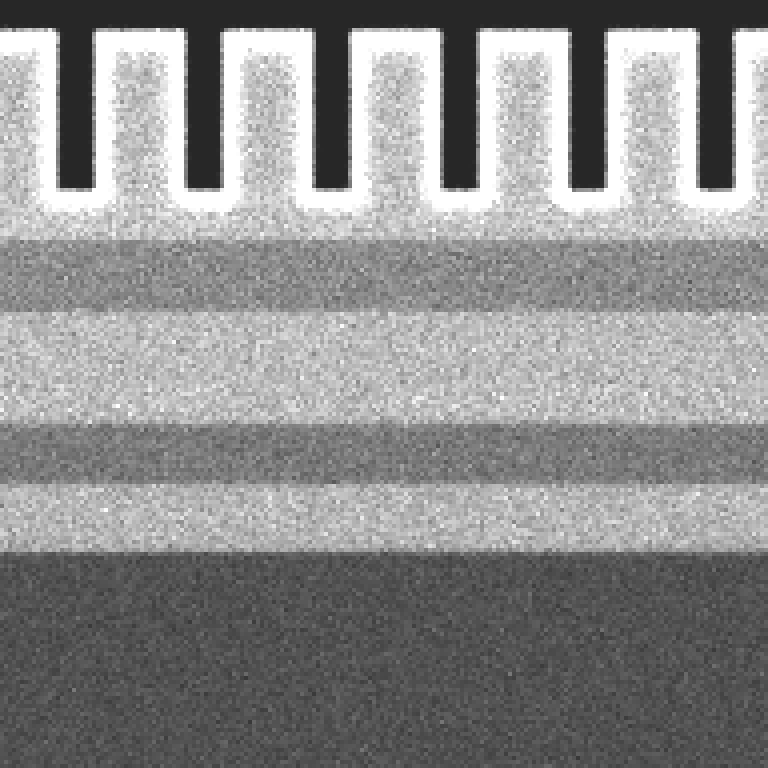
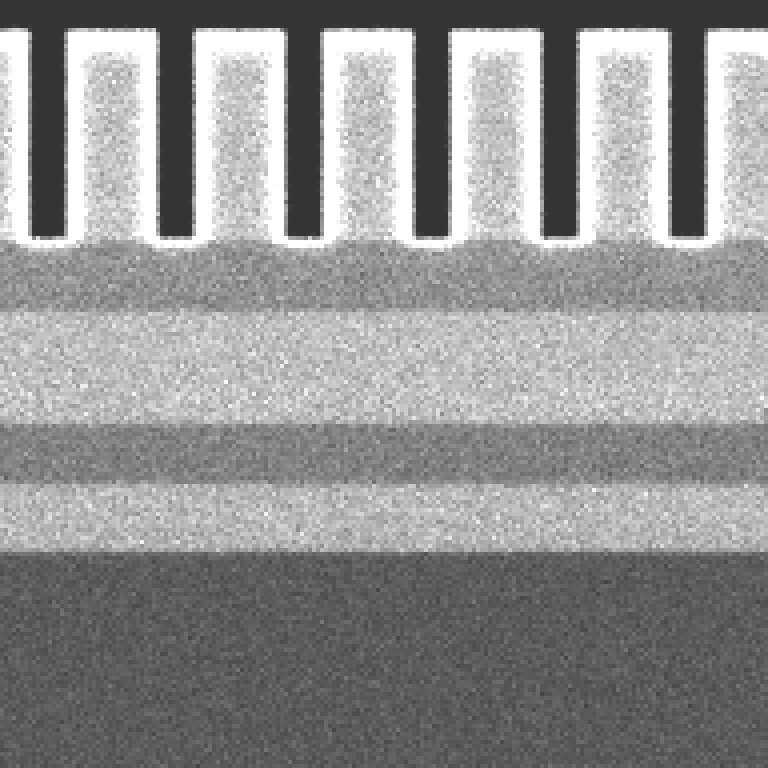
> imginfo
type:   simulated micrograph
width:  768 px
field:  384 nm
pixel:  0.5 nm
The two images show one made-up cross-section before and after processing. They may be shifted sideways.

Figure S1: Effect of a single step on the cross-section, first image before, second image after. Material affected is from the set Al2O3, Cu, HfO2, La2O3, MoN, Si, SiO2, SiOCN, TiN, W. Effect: removed Al2O3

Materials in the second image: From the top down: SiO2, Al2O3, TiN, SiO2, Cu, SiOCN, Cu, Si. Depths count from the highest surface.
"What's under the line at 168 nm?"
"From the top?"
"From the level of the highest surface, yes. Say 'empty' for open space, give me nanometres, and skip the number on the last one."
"SiO2 80, Al2O3 24, TiN 36, SiO2 36, Cu 20, SiOCN 30, Cu 34, Si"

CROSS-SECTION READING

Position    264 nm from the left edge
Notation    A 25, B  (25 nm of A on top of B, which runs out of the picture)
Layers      SiO2 80, Al2O3 24, TiN 36, SiO2 36, Cu 20, SiOCN 30, Cu 34, Si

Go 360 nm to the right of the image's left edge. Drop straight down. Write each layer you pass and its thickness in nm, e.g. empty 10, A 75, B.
SiO2 80, Al2O3 24, TiN 36, SiO2 36, Cu 20, SiOCN 30, Cu 34, Si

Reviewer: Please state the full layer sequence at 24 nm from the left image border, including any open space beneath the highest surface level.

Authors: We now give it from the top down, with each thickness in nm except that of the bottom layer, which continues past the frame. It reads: empty 104, TiN 36, SiO2 36, Cu 20, SiOCN 30, Cu 34, Si